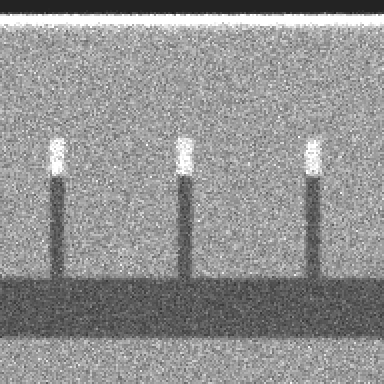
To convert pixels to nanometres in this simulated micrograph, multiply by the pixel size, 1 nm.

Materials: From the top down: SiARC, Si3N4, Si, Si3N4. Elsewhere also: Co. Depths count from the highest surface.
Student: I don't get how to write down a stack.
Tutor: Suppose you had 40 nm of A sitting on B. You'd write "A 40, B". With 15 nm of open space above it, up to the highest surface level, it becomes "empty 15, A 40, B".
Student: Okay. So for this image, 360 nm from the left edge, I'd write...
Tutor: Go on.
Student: SiARC 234, Si3N4 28, Si 60, Si3N4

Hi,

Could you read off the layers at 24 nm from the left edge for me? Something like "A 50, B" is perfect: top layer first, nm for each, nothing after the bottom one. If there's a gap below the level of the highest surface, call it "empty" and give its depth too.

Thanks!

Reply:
SiARC 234, Si3N4 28, Si 60, Si3N4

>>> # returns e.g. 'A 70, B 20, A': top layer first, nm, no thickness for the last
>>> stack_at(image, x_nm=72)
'SiARC 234, Si3N4 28, Si 60, Si3N4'